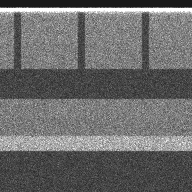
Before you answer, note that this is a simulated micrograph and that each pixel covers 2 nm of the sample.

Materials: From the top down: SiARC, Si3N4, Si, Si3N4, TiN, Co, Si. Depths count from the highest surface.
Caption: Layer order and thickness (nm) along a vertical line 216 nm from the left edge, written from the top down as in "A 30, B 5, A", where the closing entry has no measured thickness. SiARC 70, Si3N4 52, Si 60, Si3N4 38, TiN 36, Co 30, Si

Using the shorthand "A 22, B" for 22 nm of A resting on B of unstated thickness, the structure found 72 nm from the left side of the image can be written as SiARC 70, Si3N4 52, Si 60, Si3N4 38, TiN 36, Co 30, Si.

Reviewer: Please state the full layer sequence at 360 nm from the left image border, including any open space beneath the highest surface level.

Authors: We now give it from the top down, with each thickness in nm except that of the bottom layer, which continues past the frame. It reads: SiARC 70, Si3N4 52, Si 60, Si3N4 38, TiN 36, Co 30, Si